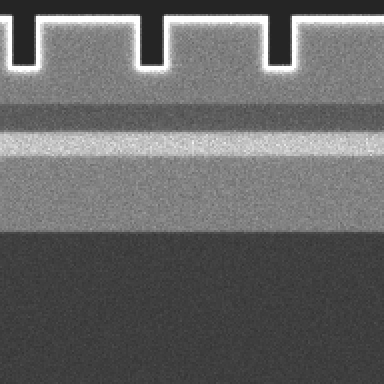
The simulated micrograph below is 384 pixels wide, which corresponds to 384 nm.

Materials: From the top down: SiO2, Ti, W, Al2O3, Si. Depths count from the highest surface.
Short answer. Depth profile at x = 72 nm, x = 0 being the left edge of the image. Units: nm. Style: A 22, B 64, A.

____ SiO2 88, Ti 28, W 24, Al2O3 76, Si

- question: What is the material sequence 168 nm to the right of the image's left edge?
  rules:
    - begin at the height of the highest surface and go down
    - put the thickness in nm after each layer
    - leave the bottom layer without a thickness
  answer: SiO2 88, Ti 28, W 24, Al2O3 76, Si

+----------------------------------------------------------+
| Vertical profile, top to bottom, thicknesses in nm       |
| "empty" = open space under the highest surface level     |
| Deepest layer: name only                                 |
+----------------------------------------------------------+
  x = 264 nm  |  SiO2 88, Ti 28, W 24, Al2O3 76, Si